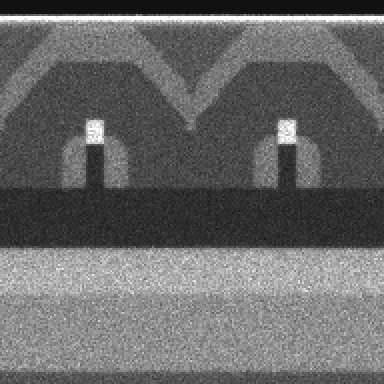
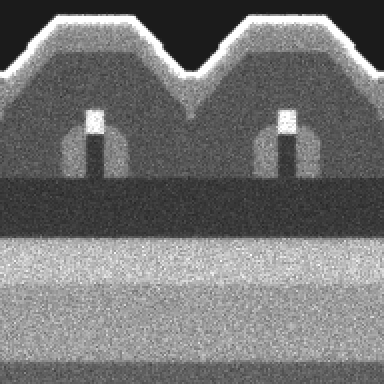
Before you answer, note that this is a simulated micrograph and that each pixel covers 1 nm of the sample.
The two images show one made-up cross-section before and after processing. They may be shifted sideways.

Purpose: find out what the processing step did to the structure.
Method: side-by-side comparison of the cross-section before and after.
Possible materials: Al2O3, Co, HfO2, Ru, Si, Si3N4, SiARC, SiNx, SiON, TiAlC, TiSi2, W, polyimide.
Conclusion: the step removed SiARC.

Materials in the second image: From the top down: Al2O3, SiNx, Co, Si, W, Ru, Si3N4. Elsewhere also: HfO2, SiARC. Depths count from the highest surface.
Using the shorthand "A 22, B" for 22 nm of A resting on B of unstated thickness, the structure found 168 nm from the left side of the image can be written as empty 40, Al2O3 36, SiNx 86, Si 60, W 46, Ru 78, Si3N4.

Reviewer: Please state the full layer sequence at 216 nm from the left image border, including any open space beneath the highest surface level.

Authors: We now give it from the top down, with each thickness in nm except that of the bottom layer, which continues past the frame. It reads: empty 36, Al2O3 36, SiNx 90, Si 60, W 46, Ru 78, Si3N4